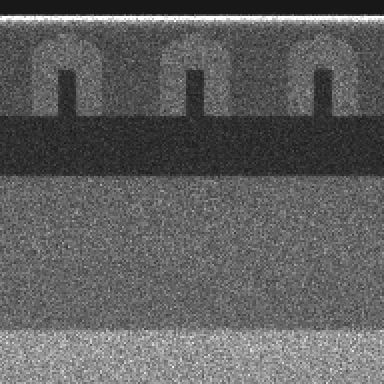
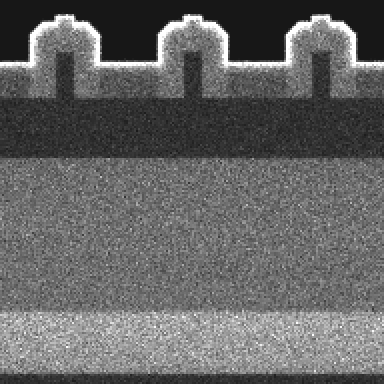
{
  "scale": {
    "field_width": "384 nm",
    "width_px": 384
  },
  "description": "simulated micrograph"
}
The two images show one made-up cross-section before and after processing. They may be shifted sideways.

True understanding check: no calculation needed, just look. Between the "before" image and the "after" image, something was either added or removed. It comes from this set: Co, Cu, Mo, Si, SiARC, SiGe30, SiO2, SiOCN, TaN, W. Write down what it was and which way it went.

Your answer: SiARC (removed)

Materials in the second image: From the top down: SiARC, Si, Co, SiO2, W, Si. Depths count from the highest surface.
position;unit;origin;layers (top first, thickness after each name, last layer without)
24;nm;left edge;empty 46, SiARC 36, Si 60, Co 90, SiO2 64, W 62, Si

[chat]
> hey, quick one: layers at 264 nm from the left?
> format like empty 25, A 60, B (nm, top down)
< empty 46, SiARC 36, Si 60, Co 90, SiO2 64, W 62, Si